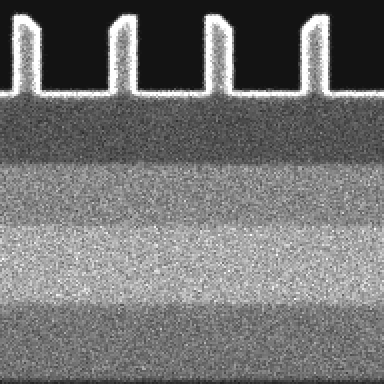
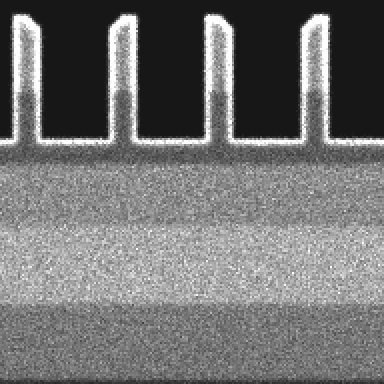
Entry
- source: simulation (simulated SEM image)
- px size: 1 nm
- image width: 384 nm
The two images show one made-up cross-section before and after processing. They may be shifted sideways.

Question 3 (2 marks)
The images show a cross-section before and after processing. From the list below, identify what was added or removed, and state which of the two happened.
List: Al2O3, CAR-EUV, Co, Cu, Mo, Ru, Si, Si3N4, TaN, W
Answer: Si3N4 was removed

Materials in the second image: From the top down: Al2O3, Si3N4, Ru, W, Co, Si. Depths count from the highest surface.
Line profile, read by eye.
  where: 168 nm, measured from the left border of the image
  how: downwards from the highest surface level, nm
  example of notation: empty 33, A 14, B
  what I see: empty 124, Si3N4 24, Ru 62, W 78, Co 76, Si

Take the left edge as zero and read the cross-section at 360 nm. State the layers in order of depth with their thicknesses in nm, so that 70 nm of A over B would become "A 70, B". empty 124, Si3N4 24, Ru 62, W 78, Co 76, Si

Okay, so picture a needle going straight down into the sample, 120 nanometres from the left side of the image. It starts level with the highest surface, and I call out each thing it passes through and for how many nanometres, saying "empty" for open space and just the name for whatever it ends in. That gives empty 2, Al2O3 74, Si3N4 72, Ru 62, W 78, Co 76, Si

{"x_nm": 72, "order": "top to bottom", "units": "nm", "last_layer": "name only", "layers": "empty 124, Si3N4 24, Ru 62, W 78, Co 76, Si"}